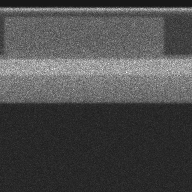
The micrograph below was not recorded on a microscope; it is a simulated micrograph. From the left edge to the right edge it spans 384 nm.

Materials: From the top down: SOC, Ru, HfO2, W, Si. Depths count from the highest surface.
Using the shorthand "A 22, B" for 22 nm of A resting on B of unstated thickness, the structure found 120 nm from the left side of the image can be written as SOC 18, Ru 84, HfO2 32, W 56, Si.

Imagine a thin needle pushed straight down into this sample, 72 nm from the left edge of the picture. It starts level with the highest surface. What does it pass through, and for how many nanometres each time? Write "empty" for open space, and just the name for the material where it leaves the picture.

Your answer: SOC 18, Ru 84, HfO2 32, W 56, Si